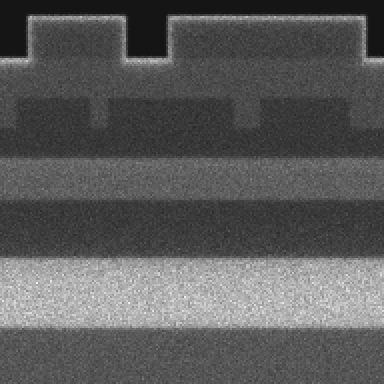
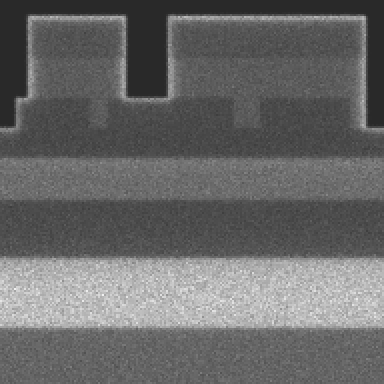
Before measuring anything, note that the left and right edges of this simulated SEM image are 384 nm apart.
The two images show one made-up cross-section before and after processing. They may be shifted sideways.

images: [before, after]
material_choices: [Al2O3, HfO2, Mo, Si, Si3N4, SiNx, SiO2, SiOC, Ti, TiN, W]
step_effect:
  removed: SiO2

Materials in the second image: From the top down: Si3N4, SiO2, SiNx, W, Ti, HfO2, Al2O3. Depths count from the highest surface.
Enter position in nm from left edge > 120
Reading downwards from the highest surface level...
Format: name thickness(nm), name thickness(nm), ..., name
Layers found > Si3N4 42, SiO2 40, SiNx 60, W 42, Ti 58, HfO2 70, Al2O3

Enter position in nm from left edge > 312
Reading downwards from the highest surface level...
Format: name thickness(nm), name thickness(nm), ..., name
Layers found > Si3N4 42, SiO2 40, SiNx 60, W 42, Ti 58, HfO2 70, Al2O3